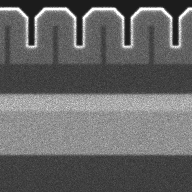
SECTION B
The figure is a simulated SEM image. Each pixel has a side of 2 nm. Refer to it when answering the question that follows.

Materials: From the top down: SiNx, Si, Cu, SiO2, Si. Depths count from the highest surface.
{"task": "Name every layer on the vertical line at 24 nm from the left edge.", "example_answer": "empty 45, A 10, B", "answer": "SiNx 112, Si 60, Cu 34, SiO2 88, Si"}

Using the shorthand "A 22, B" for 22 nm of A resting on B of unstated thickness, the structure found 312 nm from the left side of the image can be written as SiNx 112, Si 60, Cu 34, SiO2 88, Si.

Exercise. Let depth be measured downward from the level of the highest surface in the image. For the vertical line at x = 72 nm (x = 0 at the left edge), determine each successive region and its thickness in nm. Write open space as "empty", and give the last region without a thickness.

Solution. empty 16, SiNx 96, Si 60, Cu 34, SiO2 88, Si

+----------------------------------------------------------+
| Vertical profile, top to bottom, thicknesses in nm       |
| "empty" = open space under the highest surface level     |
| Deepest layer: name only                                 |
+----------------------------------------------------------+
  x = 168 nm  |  empty 16, SiNx 96, Si 60, Cu 34, SiO2 88, Si